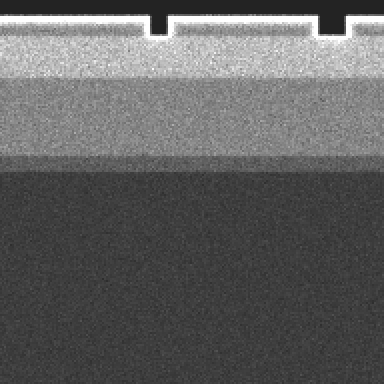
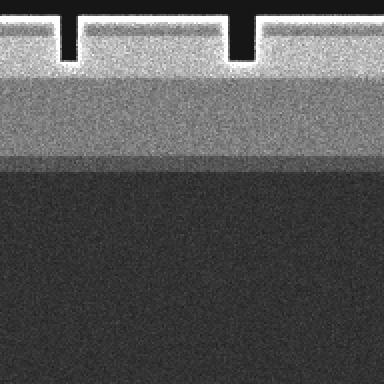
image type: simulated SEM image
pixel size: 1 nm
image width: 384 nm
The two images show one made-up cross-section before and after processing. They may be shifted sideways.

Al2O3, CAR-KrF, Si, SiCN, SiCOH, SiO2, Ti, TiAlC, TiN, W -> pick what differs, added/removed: W removed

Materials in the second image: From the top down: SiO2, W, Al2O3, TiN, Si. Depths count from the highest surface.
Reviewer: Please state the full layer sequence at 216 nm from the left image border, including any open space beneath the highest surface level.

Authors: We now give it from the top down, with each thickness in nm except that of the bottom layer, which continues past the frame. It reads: SiO2 20, W 42, Al2O3 78, TiN 16, Si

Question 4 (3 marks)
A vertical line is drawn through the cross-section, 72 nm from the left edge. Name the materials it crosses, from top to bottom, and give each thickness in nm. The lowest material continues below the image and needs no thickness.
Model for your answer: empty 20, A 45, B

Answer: empty 46, W 16, Al2O3 78, TiN 16, Si